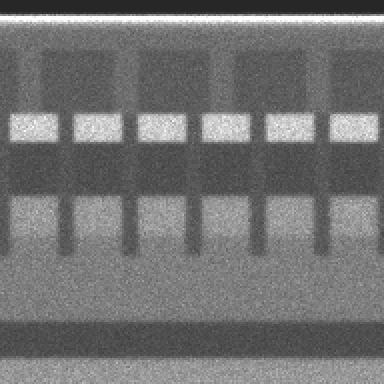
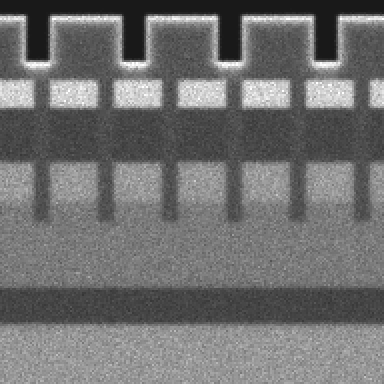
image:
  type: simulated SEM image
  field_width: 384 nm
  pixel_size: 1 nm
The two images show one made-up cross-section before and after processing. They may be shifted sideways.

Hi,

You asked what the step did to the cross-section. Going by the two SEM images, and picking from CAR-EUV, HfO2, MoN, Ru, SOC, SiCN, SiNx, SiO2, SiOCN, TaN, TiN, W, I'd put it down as SiO2, removed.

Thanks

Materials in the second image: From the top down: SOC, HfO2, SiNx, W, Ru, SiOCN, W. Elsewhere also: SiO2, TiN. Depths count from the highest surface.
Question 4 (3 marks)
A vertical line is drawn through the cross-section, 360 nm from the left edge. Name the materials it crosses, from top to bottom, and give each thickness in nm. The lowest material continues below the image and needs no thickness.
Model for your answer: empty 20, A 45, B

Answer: SOC 64, TiN 142, Ru 66, SiOCN 36, W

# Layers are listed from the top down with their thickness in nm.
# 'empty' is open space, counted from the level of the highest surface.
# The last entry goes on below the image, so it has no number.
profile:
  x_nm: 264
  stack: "SOC 64, HfO2 28, SiNx 54, W 40, Ru 86, SiOCN 36, W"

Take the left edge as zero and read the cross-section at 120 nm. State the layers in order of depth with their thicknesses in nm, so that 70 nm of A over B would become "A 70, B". SOC 64, HfO2 28, SiNx 54, W 40, Ru 86, SiOCN 36, W